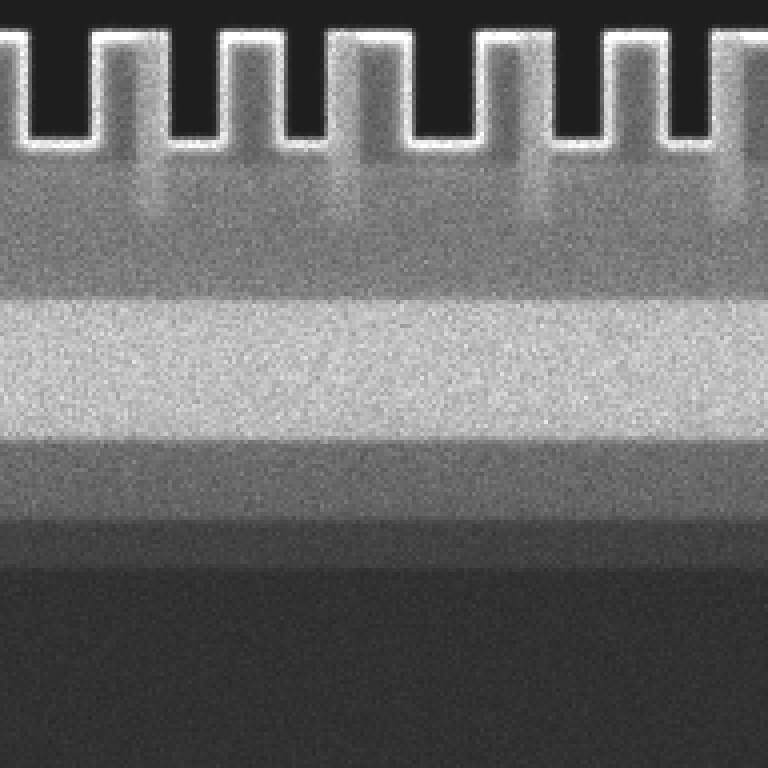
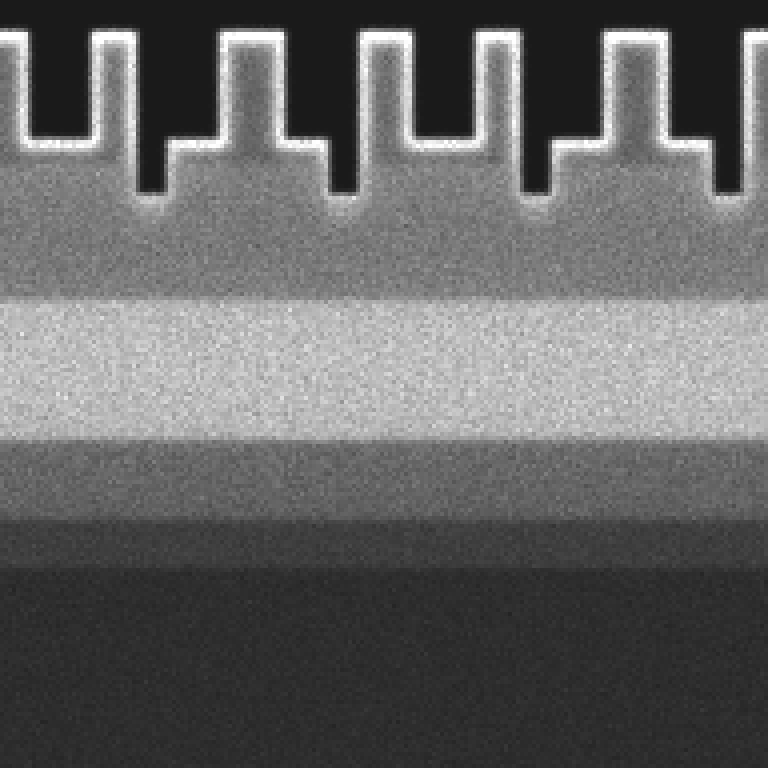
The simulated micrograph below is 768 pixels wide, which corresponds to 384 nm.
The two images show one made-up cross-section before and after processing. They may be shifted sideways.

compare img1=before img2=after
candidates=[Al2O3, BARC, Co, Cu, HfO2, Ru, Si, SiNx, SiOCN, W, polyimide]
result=removed:W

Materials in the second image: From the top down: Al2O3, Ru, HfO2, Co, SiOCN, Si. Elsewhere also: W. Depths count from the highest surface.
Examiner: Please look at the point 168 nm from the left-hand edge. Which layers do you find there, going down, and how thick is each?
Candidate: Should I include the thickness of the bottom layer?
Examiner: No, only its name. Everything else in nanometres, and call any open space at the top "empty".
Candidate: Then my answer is empty 82, W 12, Ru 40, HfO2 70, Co 40, SiOCN 24, Si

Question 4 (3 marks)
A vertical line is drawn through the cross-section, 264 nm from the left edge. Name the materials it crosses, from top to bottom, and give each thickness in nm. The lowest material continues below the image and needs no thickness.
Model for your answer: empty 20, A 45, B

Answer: empty 82, W 12, Ru 40, HfO2 70, Co 40, SiOCN 24, Si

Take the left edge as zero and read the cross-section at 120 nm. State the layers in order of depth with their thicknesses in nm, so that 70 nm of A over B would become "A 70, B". Al2O3 66, Ru 68, HfO2 70, Co 40, SiOCN 24, Si